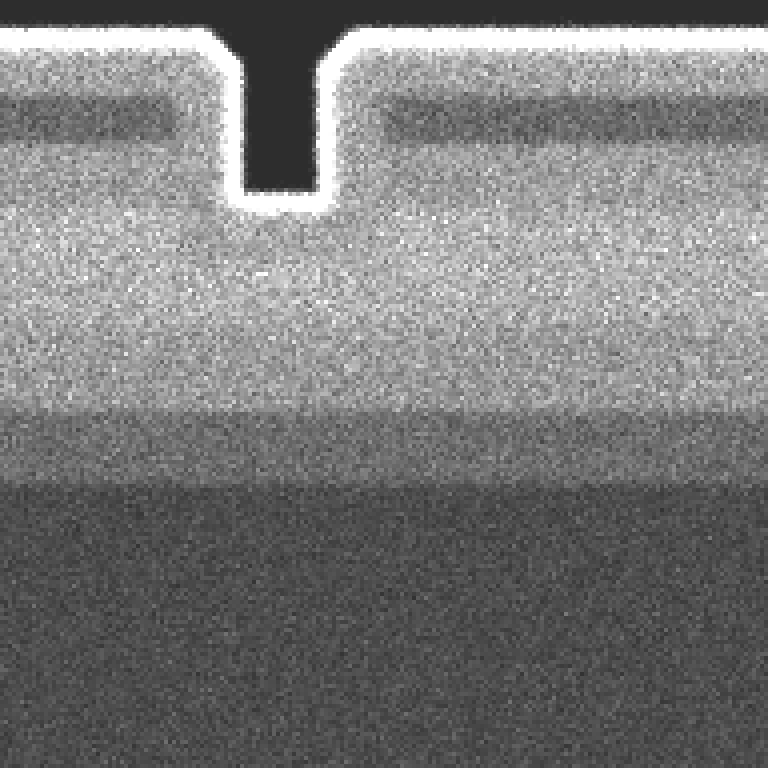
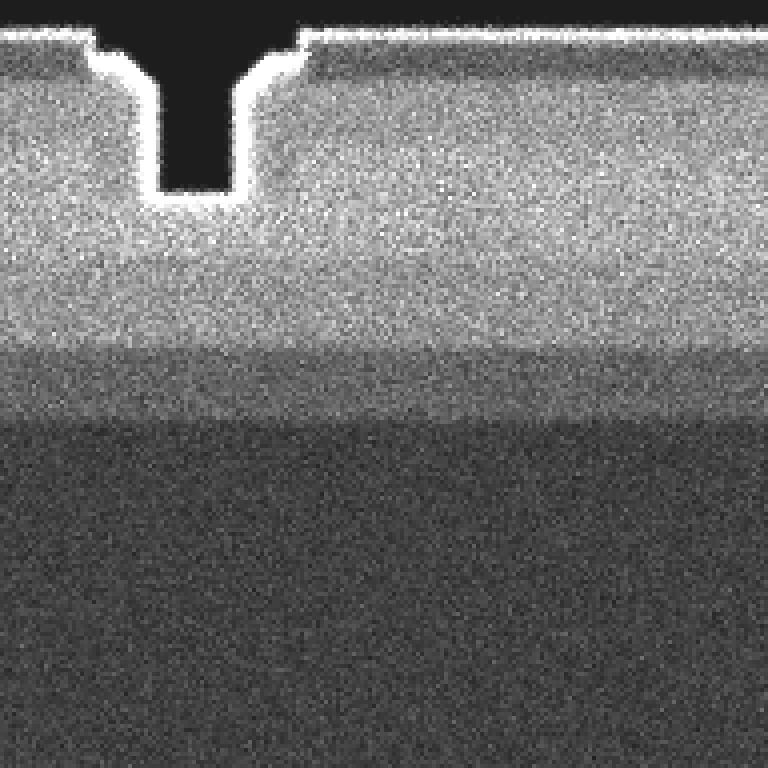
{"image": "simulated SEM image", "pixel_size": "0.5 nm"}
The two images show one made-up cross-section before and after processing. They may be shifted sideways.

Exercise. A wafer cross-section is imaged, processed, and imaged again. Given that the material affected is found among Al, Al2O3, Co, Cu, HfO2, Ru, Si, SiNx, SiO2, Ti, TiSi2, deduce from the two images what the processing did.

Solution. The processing removed Al2O3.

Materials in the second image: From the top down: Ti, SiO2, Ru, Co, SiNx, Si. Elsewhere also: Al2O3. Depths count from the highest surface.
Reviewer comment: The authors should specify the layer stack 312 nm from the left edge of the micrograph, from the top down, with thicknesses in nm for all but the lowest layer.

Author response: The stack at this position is Ti 24, SiO2 32, Ru 58, Co 44, SiNx 36, Si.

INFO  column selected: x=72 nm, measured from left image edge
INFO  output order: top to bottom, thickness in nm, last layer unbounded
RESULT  empty 24, Al2O3 58, Ru 32, Co 44, SiNx 36, Si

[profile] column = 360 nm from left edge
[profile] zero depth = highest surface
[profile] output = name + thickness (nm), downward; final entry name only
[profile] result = Ti 24, SiO2 32, Ru 58, Co 44, SiNx 36, Si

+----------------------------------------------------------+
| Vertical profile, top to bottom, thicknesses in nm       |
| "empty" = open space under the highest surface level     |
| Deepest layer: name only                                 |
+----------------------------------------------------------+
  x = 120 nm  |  empty 26, Al2O3 56, Ru 32, Co 44, SiNx 36, Si